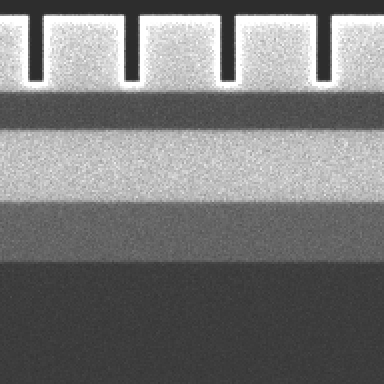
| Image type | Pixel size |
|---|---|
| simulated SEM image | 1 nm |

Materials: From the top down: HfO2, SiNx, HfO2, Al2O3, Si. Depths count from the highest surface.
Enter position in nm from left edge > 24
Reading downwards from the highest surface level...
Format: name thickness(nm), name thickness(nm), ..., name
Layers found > HfO2 76, SiNx 38, HfO2 72, Al2O3 60, Si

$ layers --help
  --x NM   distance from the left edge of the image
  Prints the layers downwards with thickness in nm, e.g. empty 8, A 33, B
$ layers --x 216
HfO2 76, SiNx 38, HfO2 72, Al2O3 60, Si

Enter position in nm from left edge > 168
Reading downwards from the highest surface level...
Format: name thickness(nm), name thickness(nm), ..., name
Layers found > HfO2 76, SiNx 38, HfO2 72, Al2O3 60, Si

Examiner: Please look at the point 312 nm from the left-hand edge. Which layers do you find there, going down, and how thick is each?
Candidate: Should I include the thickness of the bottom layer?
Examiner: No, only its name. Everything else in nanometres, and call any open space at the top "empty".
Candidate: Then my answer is HfO2 76, SiNx 38, HfO2 72, Al2O3 60, Si